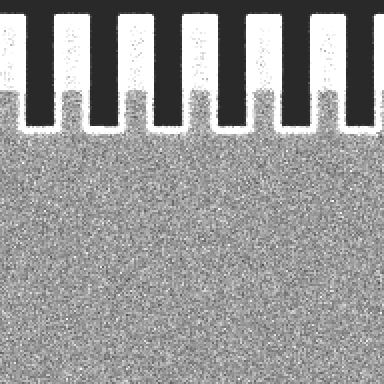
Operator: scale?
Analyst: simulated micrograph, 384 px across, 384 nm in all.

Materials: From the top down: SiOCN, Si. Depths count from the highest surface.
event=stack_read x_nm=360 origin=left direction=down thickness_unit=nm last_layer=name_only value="empty 112, Si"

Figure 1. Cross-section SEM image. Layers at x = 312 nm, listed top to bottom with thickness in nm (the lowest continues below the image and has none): SiOCN 74, Si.